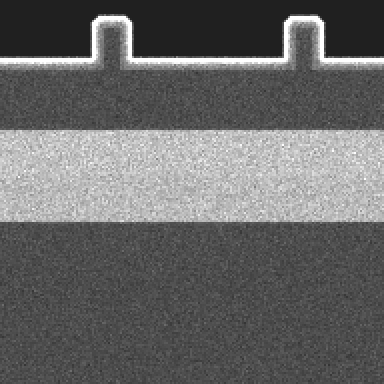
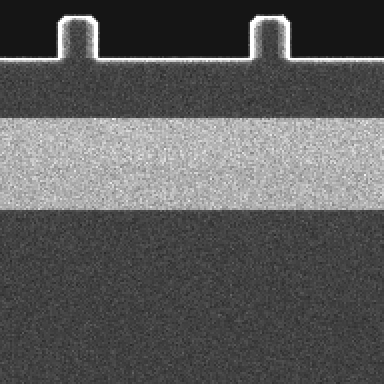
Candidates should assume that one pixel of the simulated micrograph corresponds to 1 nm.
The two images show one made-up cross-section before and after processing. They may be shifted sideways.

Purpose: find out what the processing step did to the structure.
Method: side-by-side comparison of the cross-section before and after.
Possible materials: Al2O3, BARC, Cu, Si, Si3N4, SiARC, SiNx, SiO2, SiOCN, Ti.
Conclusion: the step removed SiOCN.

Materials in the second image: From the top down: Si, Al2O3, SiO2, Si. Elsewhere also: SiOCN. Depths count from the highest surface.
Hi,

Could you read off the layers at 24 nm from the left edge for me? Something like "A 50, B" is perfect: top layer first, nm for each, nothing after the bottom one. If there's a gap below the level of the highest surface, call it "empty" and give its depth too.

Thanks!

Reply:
empty 42, Si 60, Al2O3 46, SiO2 46, Si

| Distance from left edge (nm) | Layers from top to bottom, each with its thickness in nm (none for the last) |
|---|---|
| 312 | empty 42, Si 60, Al2O3 46, SiO2 46, Si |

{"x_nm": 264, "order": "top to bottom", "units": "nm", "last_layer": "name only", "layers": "Si 102, Al2O3 46, SiO2 46, Si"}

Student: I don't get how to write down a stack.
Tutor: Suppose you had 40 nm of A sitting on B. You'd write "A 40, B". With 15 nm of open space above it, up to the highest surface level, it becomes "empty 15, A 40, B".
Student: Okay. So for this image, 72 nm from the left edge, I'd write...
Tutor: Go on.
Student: Si 102, Al2O3 46, SiO2 46, Si